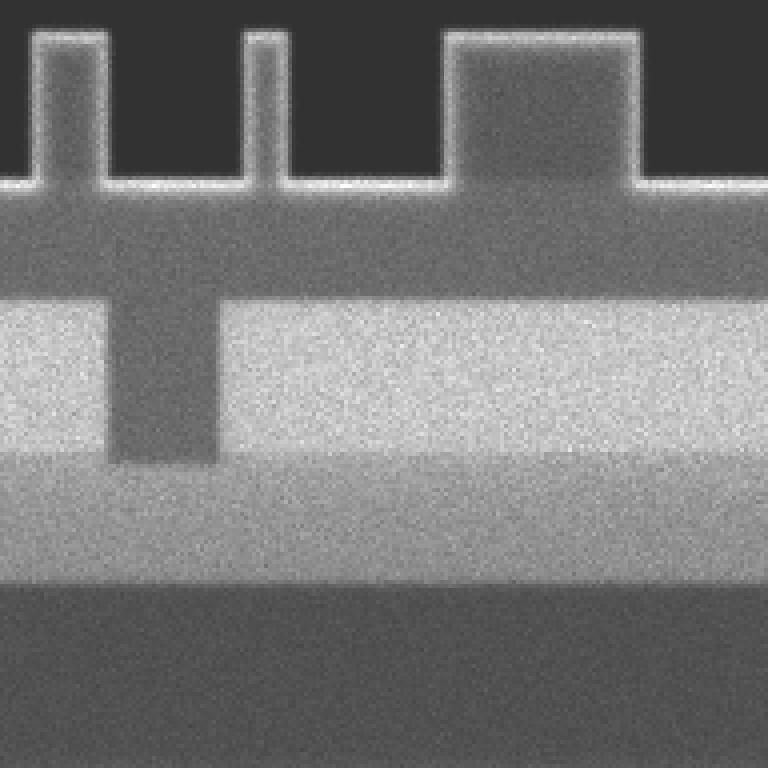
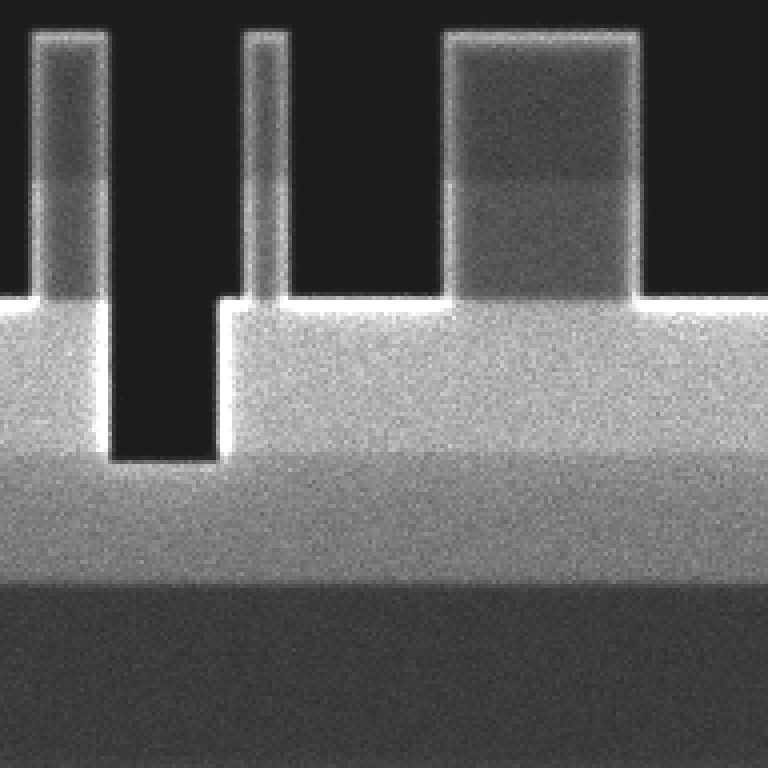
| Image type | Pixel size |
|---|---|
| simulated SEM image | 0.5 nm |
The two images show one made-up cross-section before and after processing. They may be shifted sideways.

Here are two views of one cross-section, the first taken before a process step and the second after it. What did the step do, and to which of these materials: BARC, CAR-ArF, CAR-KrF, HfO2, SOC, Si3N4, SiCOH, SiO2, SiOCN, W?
It removed SiO2.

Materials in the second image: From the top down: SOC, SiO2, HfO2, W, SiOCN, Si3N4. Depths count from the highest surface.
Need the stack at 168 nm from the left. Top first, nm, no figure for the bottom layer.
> empty 134, HfO2 76, W 66, SiOCN 88, Si3N4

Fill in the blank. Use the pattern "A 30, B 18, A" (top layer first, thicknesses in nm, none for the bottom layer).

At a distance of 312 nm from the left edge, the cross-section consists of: SOC 74, SiO2 60, HfO2 76, W 66, SiOCN 88, Si3N4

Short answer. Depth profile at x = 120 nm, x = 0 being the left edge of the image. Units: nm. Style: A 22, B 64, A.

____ empty 134, HfO2 76, W 66, SiOCN 88, Si3N4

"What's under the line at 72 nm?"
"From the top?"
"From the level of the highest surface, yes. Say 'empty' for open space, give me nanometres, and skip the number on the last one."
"empty 216, W 60, SiOCN 88, Si3N4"